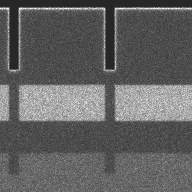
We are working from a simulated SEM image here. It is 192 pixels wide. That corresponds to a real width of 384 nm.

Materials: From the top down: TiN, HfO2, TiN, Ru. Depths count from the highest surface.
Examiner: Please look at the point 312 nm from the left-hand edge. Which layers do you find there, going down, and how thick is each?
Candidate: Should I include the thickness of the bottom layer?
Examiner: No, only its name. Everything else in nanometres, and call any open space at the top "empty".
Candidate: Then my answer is TiN 154, HfO2 72, TiN 64, Ru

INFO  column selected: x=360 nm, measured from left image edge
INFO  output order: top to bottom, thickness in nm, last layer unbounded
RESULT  TiN 154, HfO2 72, TiN 64, Ru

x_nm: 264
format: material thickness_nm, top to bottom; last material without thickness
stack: TiN 154, HfO2 72, TiN 64, Ru